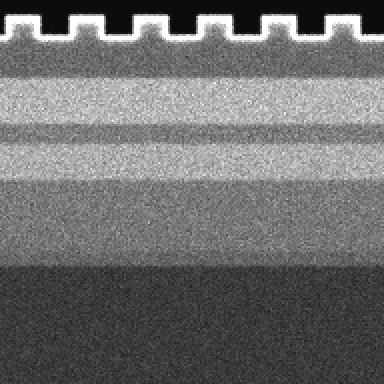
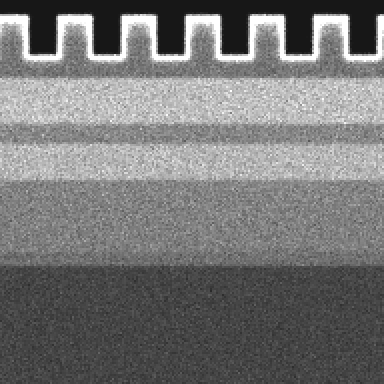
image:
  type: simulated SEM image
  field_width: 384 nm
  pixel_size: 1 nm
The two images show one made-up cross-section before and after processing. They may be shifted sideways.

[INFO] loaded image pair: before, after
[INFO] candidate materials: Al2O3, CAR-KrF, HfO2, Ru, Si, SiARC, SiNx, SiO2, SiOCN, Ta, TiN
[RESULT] removed SiNx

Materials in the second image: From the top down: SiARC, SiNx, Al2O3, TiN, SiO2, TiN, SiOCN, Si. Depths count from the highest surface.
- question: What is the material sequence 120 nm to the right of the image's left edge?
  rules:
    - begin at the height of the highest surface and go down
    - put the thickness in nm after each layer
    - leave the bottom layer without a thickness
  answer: empty 40, SiNx 22, Al2O3 46, TiN 20, SiO2 36, TiN 72, SiOCN 14, Si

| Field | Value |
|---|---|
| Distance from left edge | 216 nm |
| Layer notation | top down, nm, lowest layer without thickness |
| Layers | SiARC 20, SiNx 42, Al2O3 46, TiN 20, SiO2 36, TiN 72, SiOCN 14, Si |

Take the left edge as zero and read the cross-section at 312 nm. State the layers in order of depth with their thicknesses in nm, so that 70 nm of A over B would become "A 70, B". empty 40, SiNx 22, Al2O3 46, TiN 20, SiO2 36, TiN 72, SiOCN 14, Si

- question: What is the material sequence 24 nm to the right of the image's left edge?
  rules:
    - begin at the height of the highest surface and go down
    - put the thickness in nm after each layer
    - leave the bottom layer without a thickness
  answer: SiARC 20, SiNx 42, Al2O3 46, TiN 20, SiO2 36, TiN 72, SiOCN 14, Si